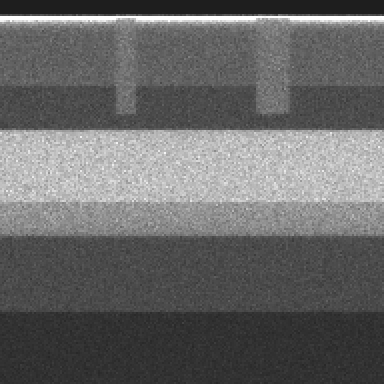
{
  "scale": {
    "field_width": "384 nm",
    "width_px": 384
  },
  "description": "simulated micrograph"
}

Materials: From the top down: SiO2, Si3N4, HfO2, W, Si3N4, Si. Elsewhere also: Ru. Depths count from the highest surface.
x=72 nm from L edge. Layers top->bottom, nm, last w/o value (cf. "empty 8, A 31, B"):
SiO2 70, Si3N4 44, HfO2 72, W 34, Si3N4 76, Si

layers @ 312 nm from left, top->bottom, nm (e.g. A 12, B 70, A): SiO2 70, Si3N4 44, HfO2 72, W 34, Si3N4 76, Si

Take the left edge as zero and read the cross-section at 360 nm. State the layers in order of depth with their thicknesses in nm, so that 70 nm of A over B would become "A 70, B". SiO2 70, Si3N4 44, HfO2 72, W 34, Si3N4 76, Si